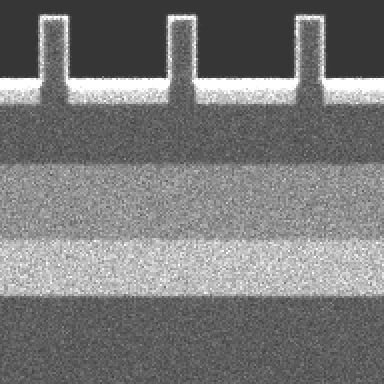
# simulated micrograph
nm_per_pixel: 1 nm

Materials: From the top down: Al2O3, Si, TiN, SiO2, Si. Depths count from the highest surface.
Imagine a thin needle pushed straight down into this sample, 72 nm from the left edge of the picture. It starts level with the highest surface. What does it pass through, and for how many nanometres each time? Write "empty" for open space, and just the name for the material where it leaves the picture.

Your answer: empty 64, Al2O3 24, Si 60, TiN 76, SiO2 56, Si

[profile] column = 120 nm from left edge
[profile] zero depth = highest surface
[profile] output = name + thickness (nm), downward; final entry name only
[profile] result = empty 64, Al2O3 24, Si 60, TiN 76, SiO2 56, Si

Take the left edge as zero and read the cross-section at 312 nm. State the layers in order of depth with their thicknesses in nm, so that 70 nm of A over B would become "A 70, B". Si 148, TiN 76, SiO2 56, Si